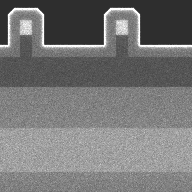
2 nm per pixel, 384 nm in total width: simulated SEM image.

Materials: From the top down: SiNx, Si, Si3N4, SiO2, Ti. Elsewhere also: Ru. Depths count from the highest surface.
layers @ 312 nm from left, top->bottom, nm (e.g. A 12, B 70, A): empty 74, SiNx 24, Si 60, Si3N4 82, SiO2 88, Ti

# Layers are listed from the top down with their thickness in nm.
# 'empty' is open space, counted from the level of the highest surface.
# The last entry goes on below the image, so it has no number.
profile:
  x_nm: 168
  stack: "empty 74, SiNx 24, Si 60, Si3N4 82, SiO2 88, Ti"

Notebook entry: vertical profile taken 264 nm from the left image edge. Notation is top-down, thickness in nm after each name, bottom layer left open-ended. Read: SiNx 98, Si 60, Si3N4 82, SiO2 88, Ti